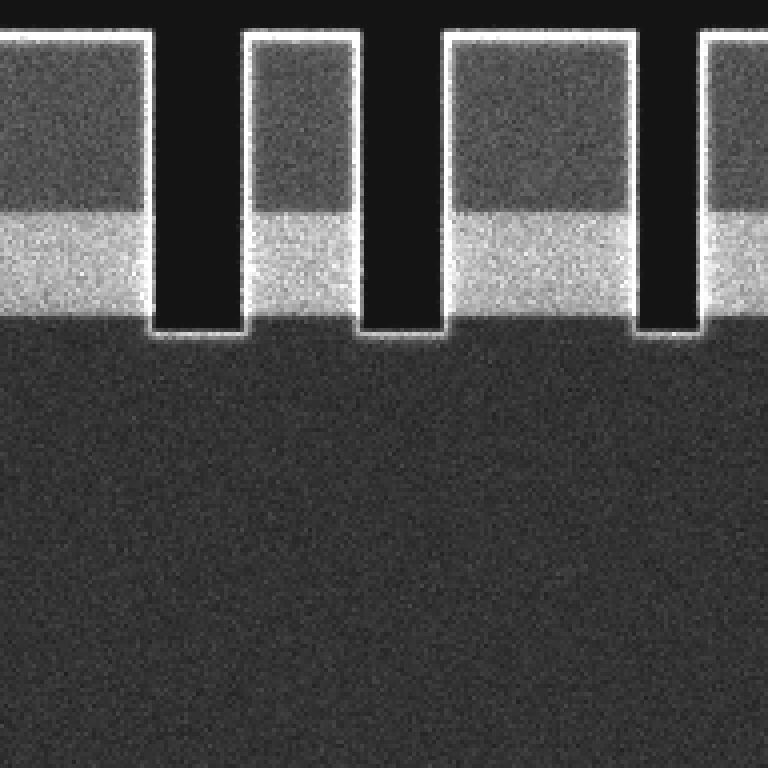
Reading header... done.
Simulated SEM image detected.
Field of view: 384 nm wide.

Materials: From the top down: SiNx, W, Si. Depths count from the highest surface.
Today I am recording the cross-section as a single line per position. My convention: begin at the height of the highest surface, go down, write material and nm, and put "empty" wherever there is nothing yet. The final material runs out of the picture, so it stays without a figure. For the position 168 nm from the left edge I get SiNx 90, W 52, Si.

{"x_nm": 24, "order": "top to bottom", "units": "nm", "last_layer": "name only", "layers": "SiNx 90, W 52, Si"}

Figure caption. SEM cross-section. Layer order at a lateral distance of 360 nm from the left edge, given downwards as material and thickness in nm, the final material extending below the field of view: SiNx 90, W 52, Si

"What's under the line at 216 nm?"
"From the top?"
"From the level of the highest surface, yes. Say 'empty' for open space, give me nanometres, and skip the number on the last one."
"empty 150, Si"